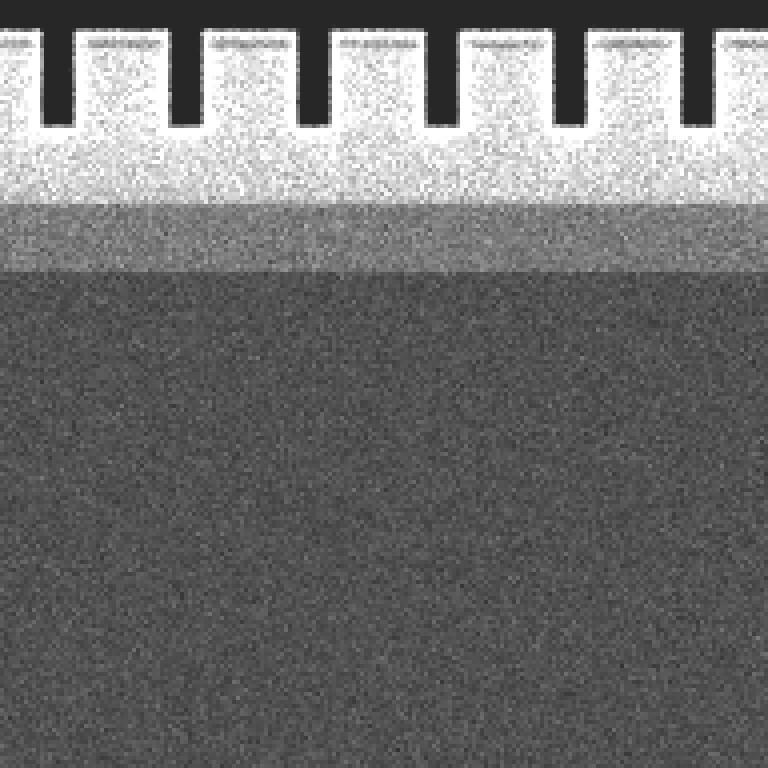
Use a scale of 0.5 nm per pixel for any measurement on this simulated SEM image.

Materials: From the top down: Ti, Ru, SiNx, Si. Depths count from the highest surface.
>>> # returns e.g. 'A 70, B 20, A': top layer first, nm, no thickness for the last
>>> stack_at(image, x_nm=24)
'empty 48, Ru 38, SiNx 34, Si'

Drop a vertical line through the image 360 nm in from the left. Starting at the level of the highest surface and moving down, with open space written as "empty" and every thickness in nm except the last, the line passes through Ti 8, Ru 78, SiNx 34, Si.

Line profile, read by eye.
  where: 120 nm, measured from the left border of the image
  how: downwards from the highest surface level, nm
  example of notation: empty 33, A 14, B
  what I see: Ti 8, Ru 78, SiNx 34, Si